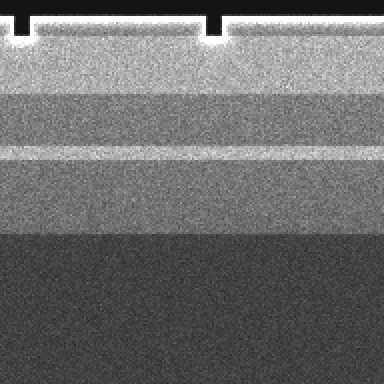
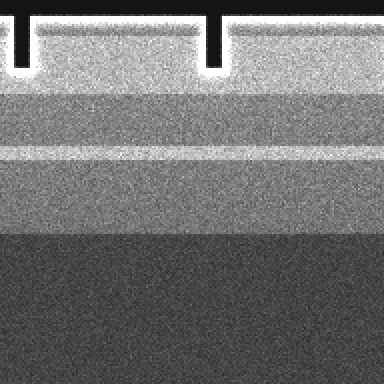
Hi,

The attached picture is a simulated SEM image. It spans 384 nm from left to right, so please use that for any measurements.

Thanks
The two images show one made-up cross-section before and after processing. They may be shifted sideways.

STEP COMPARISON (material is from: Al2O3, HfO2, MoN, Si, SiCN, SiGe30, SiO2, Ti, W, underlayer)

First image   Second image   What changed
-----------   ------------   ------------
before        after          SiO2, removed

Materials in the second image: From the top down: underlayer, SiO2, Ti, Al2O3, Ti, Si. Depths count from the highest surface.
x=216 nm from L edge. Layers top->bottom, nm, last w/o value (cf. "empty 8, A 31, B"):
empty 52, SiO2 26, Ti 52, Al2O3 14, Ti 74, Si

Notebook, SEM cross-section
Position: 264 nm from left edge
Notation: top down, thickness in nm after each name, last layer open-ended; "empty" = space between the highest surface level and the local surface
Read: underlayer 20, SiO2 58, Ti 52, Al2O3 14, Ti 74, Si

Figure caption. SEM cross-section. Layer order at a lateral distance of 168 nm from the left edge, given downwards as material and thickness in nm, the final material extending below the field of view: underlayer 20, SiO2 58, Ti 52, Al2O3 14, Ti 74, Si